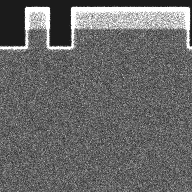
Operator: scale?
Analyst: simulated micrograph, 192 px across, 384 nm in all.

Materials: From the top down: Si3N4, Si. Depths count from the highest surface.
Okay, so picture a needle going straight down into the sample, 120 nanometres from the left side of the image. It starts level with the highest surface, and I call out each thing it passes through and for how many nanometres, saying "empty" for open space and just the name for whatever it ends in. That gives empty 78, Si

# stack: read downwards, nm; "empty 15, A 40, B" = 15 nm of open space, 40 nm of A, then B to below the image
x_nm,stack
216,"Si3N4 42, Si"